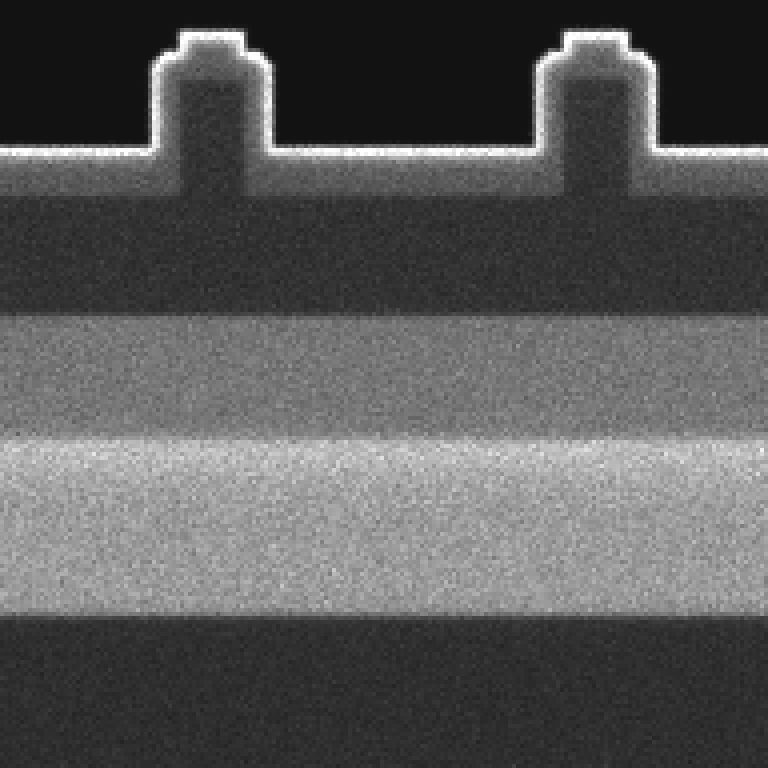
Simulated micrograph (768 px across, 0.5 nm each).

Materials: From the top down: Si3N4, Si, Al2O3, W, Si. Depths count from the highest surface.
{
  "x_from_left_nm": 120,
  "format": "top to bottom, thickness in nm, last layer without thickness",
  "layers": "Si3N4 24, Si 118, Al2O3 62, W 88, Si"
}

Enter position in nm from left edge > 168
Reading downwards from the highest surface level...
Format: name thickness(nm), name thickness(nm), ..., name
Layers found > empty 58, Si3N4 24, Si 60, Al2O3 62, W 88, Si